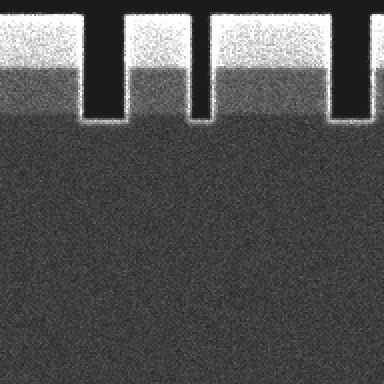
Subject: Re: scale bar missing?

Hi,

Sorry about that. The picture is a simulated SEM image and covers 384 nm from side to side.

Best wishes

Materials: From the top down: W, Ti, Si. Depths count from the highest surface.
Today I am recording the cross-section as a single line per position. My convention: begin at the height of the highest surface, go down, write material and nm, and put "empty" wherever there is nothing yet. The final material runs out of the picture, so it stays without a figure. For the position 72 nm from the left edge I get W 52, Ti 46, Si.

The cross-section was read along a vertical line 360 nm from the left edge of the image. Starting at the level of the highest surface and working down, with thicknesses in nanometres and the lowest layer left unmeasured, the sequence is empty 104, Si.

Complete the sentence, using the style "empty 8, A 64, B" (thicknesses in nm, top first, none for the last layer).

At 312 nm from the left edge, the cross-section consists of W 52, Ti 46, Si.